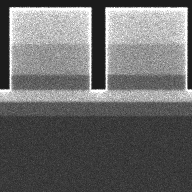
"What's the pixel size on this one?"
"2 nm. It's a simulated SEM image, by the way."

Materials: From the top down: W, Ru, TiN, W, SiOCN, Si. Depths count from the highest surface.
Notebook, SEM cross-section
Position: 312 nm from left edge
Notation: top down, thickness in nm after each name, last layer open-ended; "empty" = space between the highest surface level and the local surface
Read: W 72, Ru 62, TiN 30, W 24, SiOCN 28, Si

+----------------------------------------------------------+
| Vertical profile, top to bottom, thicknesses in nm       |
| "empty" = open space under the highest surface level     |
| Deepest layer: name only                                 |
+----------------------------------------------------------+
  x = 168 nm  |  W 72, Ru 62, TiN 30, W 24, SiOCN 28, Si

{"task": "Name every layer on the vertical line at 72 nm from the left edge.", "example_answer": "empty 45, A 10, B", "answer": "W 72, Ru 62, TiN 30, W 24, SiOCN 28, Si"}